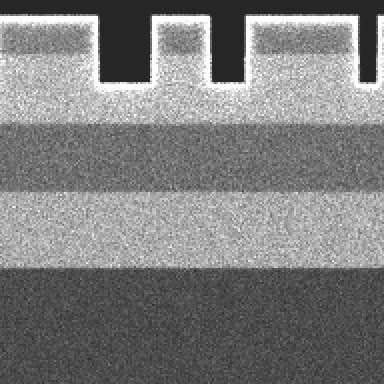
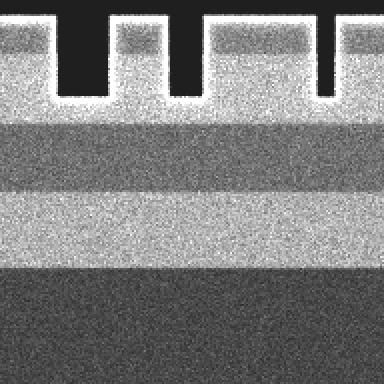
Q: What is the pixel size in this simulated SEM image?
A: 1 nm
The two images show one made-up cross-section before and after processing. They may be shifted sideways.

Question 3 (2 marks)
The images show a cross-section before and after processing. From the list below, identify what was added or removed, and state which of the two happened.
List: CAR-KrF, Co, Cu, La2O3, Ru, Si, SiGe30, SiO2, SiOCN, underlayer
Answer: Ru was removed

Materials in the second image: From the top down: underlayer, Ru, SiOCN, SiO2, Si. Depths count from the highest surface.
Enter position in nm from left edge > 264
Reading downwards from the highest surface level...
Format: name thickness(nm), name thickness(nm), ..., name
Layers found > underlayer 38, Ru 70, SiOCN 68, SiO2 76, Si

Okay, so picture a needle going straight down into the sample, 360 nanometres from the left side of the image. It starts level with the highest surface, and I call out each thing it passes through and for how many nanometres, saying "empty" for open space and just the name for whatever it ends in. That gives underlayer 38, Ru 70, SiOCN 68, SiO2 76, Si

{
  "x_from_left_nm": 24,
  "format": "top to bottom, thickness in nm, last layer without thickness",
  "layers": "underlayer 38, Ru 70, SiOCN 68, SiO2 76, Si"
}